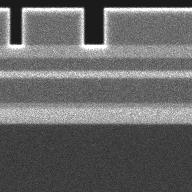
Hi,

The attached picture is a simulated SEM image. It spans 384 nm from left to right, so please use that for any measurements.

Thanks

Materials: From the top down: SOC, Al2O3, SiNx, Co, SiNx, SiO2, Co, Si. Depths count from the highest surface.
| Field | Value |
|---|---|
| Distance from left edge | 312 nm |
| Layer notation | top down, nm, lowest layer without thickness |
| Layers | SOC 74, Al2O3 26, SiNx 26, Co 14, SiNx 50, SiO2 10, Co 32, Si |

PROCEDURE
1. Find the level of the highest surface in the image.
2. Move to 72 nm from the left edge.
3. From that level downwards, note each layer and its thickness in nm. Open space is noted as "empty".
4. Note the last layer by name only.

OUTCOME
SOC 74, Al2O3 26, SiNx 26, Co 14, SiNx 50, SiO2 10, Co 32, Si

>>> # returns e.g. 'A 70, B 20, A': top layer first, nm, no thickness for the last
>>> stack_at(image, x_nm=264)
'SOC 74, Al2O3 26, SiNx 26, Co 14, SiNx 50, SiO2 10, Co 32, Si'